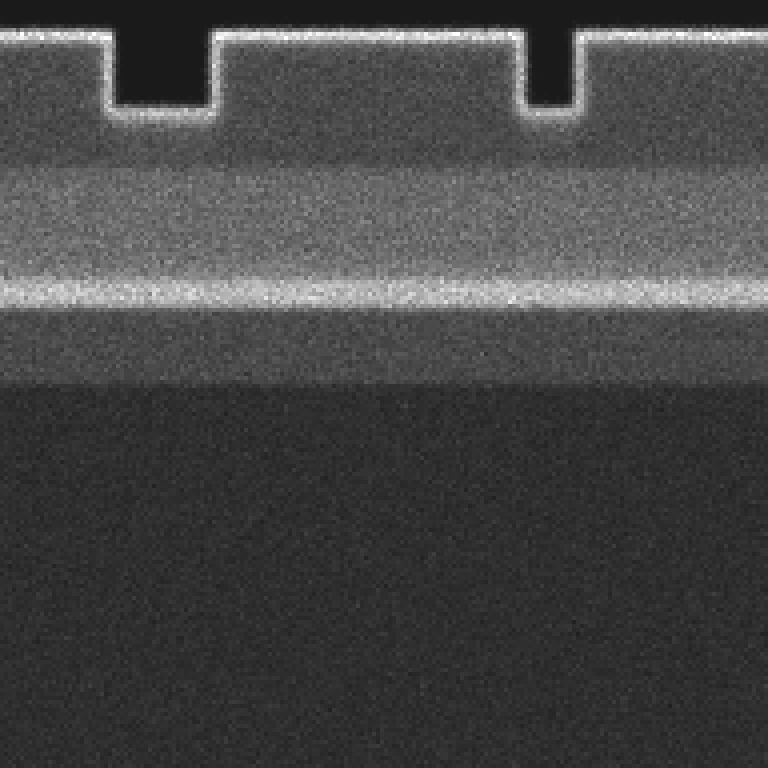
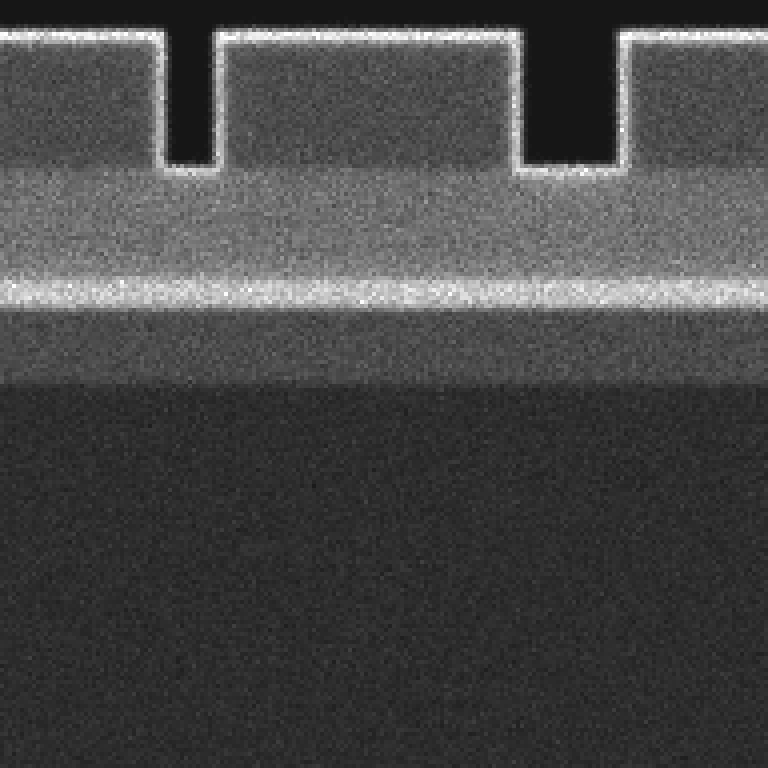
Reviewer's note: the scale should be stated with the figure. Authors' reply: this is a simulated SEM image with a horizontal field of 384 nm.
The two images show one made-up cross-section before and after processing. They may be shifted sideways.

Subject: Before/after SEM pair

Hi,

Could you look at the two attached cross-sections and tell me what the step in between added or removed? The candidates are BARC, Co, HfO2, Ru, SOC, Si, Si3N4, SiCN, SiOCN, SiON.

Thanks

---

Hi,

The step removed SOC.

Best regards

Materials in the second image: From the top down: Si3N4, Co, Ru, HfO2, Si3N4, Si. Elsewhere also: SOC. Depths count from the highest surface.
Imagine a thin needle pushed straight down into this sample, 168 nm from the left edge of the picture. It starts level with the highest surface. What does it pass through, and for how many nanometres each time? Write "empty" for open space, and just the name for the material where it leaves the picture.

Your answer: Si3N4 68, Co 46, Ru 10, HfO2 14, Si3N4 38, Si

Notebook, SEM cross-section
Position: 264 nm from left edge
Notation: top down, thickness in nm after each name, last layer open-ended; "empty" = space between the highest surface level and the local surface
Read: empty 68, Co 46, Ru 10, HfO2 14, Si3N4 38, Si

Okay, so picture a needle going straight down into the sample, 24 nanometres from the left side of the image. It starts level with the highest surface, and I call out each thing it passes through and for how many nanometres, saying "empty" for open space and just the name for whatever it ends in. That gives Si3N4 68, Co 46, Ru 10, HfO2 14, Si3N4 38, Si